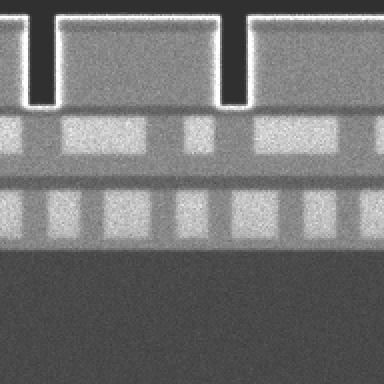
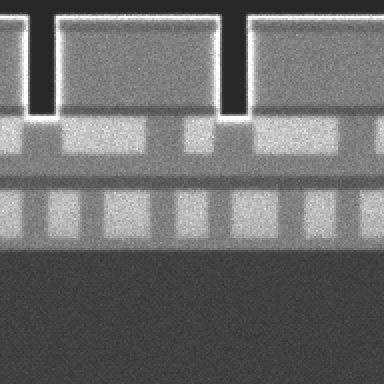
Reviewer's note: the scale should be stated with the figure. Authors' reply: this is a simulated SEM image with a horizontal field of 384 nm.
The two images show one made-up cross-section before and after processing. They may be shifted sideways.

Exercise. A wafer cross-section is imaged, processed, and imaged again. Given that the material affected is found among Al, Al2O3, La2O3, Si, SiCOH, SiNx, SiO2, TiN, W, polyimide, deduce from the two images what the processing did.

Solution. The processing removed SiNx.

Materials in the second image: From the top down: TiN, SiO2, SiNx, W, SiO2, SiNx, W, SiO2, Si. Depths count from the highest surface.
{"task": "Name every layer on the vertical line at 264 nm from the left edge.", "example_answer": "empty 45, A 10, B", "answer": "TiN 16, SiO2 74, SiNx 10, W 38, SiO2 22, SiNx 14, W 48, SiO2 12, Si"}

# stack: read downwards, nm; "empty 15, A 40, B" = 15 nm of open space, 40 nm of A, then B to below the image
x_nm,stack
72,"TiN 16, SiO2 74, SiNx 10, W 38, SiO2 22, SiNx 14, W 48, SiO2 12, Si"